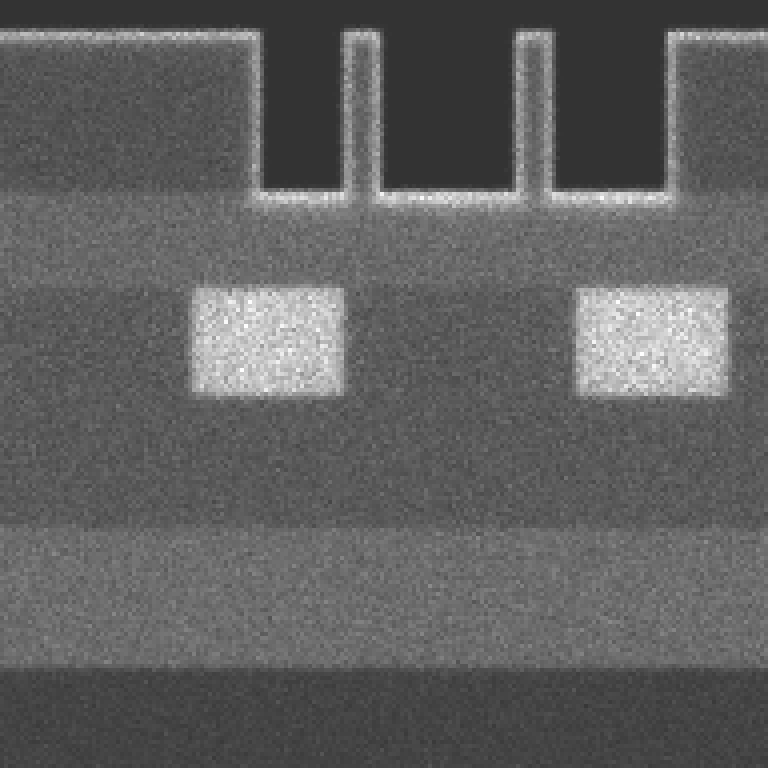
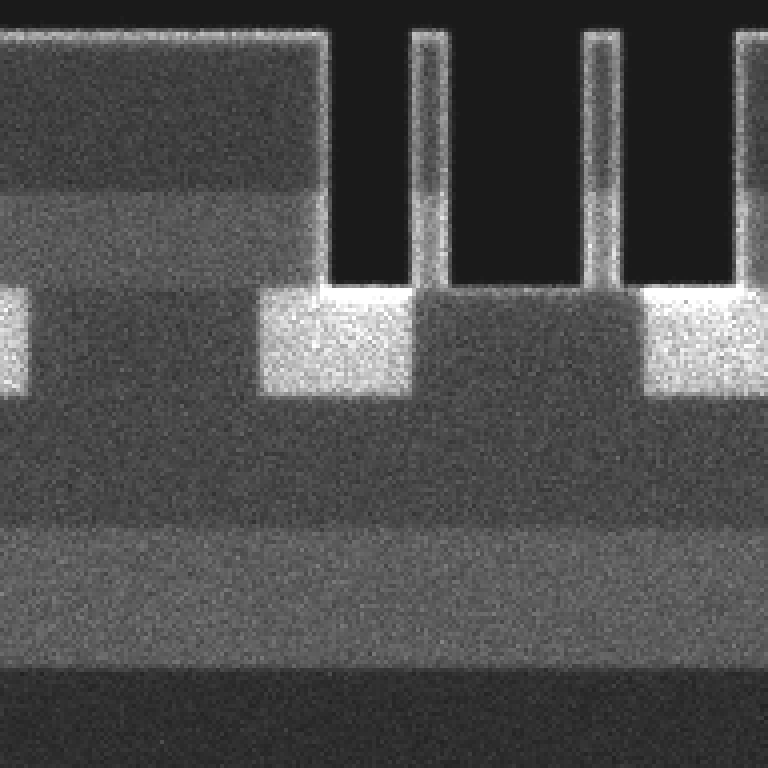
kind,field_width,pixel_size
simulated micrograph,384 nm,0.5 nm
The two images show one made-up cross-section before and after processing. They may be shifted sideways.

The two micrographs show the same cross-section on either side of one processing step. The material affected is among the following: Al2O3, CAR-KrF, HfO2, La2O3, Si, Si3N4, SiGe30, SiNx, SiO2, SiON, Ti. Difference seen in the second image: SiO2 removed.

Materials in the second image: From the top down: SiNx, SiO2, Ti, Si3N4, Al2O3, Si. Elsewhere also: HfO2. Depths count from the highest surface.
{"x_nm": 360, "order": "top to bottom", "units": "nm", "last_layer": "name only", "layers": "empty 128, HfO2 54, Si3N4 66, Al2O3 70, Si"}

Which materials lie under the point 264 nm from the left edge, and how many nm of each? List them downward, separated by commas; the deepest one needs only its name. empty 128, Ti 48, Si3N4 72, Al2O3 70, Si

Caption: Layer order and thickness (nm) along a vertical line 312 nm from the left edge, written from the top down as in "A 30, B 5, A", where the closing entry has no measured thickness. empty 128, Ti 48, Si3N4 72, Al2O3 70, Si